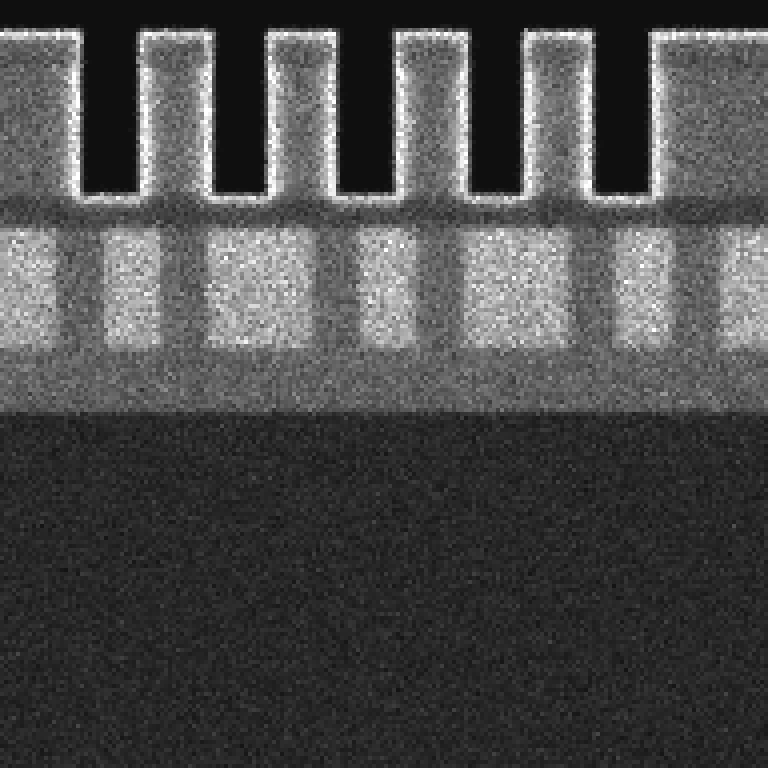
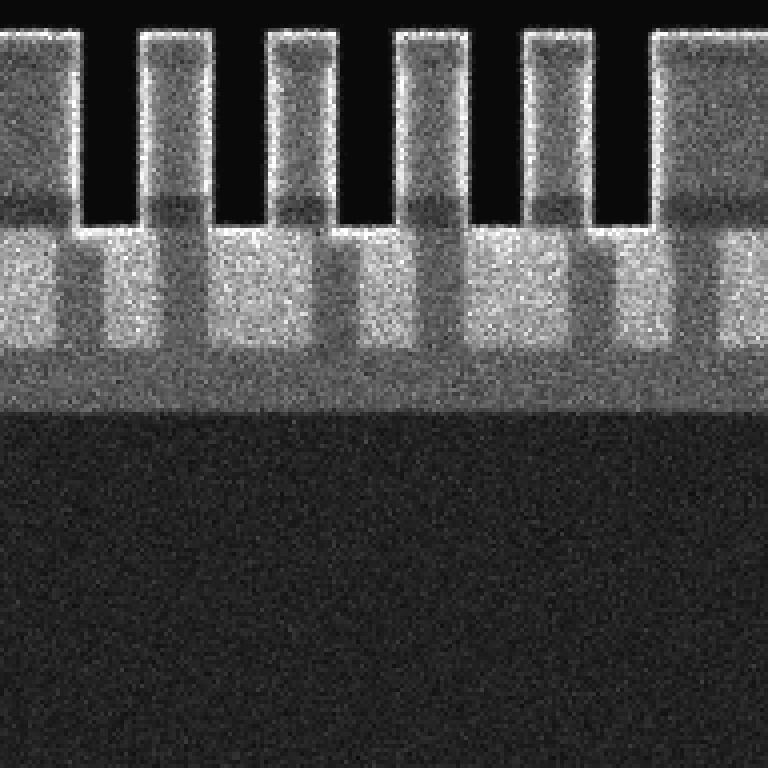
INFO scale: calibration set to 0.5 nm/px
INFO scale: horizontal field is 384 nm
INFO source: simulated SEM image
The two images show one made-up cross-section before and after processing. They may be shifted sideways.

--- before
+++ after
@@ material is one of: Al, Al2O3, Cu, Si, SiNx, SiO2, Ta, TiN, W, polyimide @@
SiNx removed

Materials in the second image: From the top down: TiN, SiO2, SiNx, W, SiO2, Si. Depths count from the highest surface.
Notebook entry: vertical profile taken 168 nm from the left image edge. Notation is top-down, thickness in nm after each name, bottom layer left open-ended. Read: empty 98, SiO2 92, Si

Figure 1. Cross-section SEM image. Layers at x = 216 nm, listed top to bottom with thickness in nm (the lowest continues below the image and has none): TiN 18, SiO2 64, SiNx 16, SiO2 92, Si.